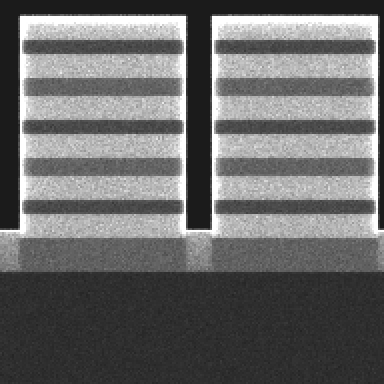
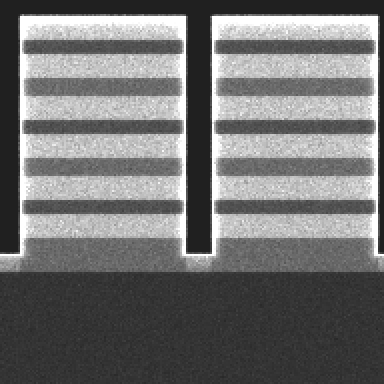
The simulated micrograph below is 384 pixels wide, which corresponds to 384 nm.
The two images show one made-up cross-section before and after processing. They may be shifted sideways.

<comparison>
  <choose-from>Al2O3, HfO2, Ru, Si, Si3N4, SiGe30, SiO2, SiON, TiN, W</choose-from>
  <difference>W removed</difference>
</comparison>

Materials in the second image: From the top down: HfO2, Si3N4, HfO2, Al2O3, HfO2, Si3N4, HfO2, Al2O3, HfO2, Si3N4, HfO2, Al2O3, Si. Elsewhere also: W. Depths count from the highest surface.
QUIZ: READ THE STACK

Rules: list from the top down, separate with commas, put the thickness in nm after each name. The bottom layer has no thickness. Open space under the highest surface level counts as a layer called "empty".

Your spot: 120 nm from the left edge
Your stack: HfO2 24, Si3N4 14, HfO2 24, Al2O3 18, HfO2 24, Si3N4 14, HfO2 24, Al2O3 18, HfO2 24, Si3N4 14, HfO2 24, Al2O3 34, Si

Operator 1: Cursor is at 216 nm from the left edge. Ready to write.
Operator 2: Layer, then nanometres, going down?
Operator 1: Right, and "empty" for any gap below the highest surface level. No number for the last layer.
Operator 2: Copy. HfO2 24, Si3N4 14, HfO2 24, Al2O3 18, HfO2 24, Si3N4 14, HfO2 24, Al2O3 18, HfO2 24, Si3N4 14, HfO2 24, Al2O3 34, Si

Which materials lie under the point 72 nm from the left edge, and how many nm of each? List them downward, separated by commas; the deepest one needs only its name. HfO2 24, Si3N4 14, HfO2 24, Al2O3 18, HfO2 24, Si3N4 14, HfO2 24, Al2O3 18, HfO2 24, Si3N4 14, HfO2 24, Al2O3 34, Si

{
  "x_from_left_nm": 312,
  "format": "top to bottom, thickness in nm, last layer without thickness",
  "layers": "HfO2 24, Si3N4 14, HfO2 24, Al2O3 18, HfO2 24, Si3N4 14, HfO2 24, Al2O3 18, HfO2 24, Si3N4 14, HfO2 24, Al2O3 34, Si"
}